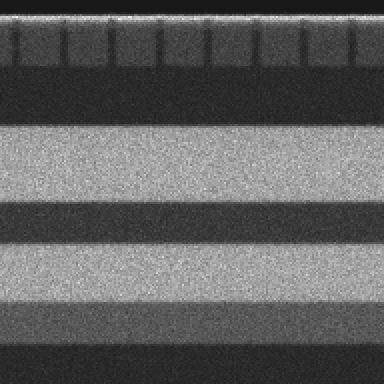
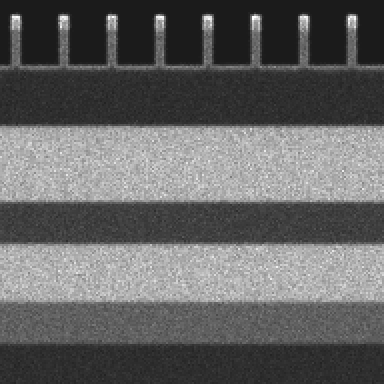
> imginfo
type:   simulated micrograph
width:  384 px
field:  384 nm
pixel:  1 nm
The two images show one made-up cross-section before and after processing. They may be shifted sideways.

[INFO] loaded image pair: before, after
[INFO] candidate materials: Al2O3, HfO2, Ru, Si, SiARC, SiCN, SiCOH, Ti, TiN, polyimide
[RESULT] removed SiARC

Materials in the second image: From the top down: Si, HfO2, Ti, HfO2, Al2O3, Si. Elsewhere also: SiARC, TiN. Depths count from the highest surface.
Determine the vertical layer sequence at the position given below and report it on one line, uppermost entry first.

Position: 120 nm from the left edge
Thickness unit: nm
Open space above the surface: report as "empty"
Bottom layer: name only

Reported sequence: empty 50, Si 60, HfO2 76, Ti 42, HfO2 58, Al2O3 42, Si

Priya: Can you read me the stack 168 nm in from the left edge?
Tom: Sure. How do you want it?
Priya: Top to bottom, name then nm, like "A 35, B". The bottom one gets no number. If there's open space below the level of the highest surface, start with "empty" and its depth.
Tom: empty 50, Si 60, HfO2 76, Ti 42, HfO2 58, Al2O3 42, Si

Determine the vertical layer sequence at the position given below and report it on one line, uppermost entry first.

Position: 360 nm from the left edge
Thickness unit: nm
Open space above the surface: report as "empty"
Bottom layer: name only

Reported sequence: empty 50, Si 60, HfO2 76, Ti 42, HfO2 58, Al2O3 42, Si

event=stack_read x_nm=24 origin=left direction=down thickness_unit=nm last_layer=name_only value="empty 50, Si 60, HfO2 76, Ti 42, HfO2 58, Al2O3 42, Si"